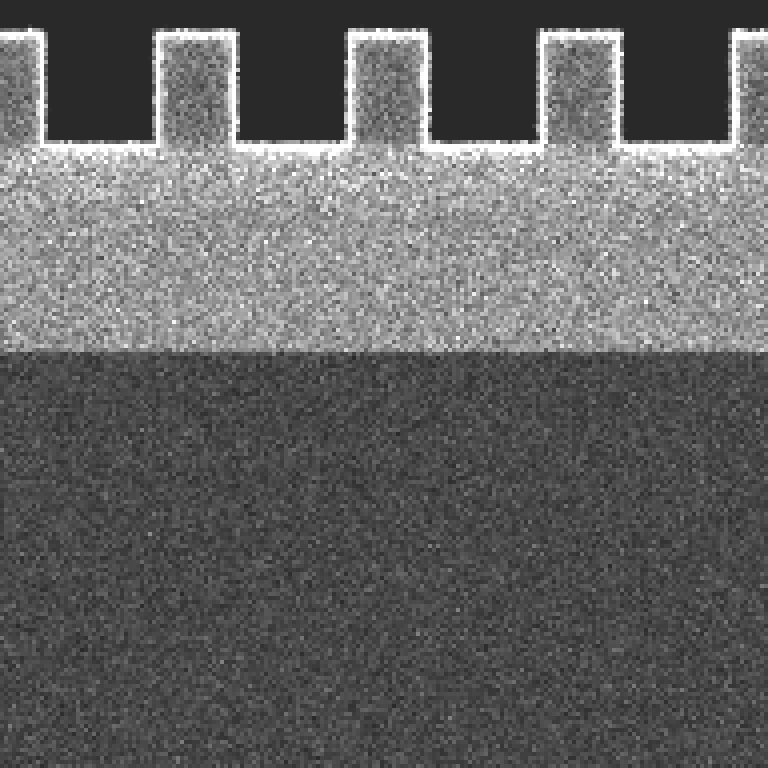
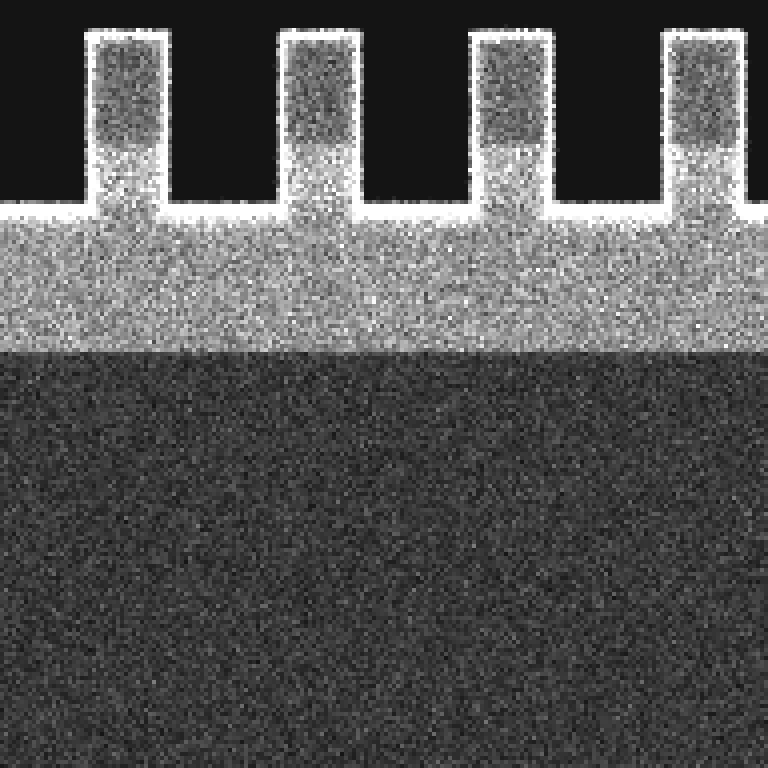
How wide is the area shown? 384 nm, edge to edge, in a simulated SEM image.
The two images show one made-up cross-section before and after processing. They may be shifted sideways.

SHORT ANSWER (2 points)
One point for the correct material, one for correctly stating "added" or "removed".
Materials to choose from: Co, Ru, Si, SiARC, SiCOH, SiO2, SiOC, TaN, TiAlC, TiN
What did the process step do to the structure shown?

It removed Ru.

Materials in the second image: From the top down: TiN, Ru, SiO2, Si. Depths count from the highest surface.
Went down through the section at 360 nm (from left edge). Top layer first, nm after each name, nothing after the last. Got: TiN 56, Ru 30, SiO2 74, Si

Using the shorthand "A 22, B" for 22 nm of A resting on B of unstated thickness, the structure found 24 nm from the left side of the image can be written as empty 86, SiO2 74, Si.